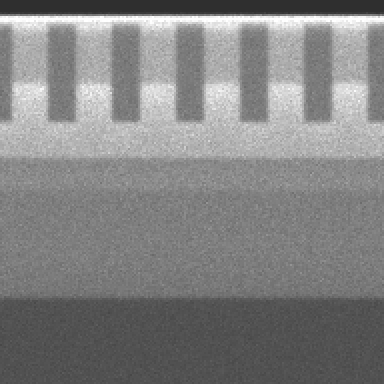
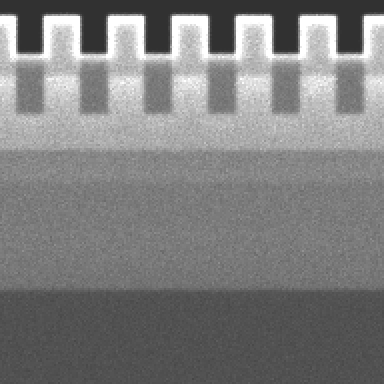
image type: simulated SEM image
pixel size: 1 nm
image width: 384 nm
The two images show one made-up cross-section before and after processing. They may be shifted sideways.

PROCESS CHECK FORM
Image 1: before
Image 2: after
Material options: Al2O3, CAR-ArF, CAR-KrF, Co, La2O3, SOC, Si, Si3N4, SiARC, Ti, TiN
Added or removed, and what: removed, SOC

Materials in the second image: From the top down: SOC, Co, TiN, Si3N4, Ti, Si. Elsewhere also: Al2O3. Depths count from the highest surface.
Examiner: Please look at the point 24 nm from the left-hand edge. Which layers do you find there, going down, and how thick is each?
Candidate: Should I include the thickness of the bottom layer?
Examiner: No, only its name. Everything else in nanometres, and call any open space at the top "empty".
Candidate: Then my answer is empty 38, SOC 60, Co 36, TiN 32, Si3N4 56, Ti 52, Si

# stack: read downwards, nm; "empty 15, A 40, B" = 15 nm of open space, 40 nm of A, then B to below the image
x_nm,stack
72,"Al2O3 60, Co 74, TiN 32, Si3N4 56, Ti 52, Si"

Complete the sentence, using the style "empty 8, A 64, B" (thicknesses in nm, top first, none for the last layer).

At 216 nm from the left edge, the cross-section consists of empty 38, SOC 60, Co 36, TiN 32, Si3N4 56, Ti 52, Si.